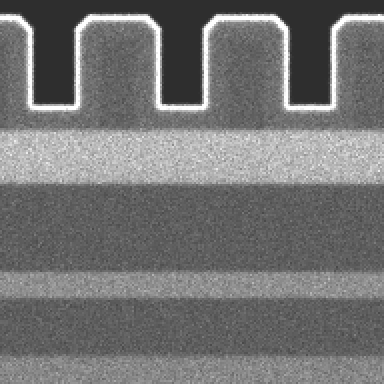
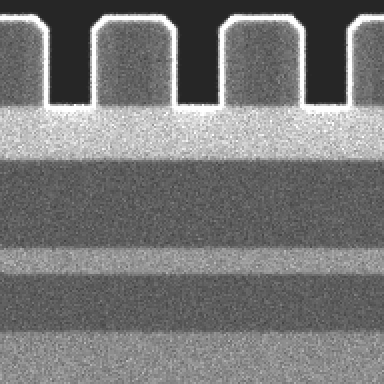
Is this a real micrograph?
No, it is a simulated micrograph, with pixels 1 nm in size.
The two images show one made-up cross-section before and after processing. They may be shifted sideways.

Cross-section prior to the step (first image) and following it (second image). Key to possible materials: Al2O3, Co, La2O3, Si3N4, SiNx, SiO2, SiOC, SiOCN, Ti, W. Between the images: Si3N4 was removed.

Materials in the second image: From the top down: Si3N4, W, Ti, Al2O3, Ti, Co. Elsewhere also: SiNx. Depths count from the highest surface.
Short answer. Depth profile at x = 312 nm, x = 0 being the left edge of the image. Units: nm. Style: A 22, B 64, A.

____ empty 90, W 54, Ti 88, Al2O3 26, Ti 58, Co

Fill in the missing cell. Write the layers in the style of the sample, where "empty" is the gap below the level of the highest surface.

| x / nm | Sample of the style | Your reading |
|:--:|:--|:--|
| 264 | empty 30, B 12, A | SiNx 90, W 54, Ti 88, Al2O3 26, Ti 58, Co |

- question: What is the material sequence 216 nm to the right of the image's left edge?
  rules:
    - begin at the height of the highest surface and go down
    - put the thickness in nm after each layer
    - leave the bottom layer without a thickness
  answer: empty 90, W 54, Ti 88, Al2O3 26, Ti 58, Co